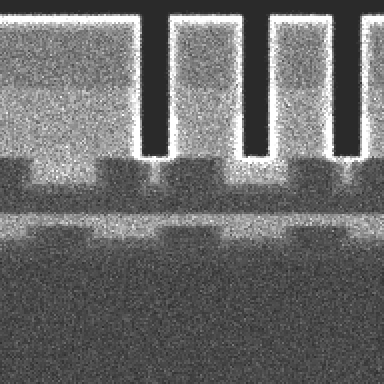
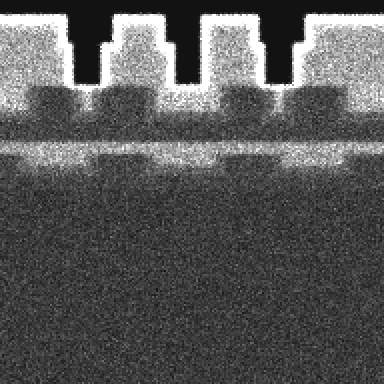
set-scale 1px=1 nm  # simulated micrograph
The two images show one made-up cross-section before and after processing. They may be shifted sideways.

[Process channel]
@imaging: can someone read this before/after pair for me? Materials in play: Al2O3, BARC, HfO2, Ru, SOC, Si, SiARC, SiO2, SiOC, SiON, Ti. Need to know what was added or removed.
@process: SOC removed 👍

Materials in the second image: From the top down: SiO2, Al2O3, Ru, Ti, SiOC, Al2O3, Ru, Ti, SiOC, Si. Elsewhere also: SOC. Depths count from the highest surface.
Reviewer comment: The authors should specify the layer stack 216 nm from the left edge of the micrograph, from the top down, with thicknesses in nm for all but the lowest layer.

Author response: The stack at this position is SiO2 54, Al2O3 16, Ru 26, Ti 10, SiOC 20, Al2O3 12, Ti 22, SiOC 14, Si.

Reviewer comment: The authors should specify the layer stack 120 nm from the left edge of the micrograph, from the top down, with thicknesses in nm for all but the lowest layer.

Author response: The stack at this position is SiO2 54, Al2O3 16, SiOC 56, Al2O3 12, SiOC 36, Si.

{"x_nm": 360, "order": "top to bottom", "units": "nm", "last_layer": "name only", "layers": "SiO2 54, Al2O3 16, Ru 26, Ti 10, SiOC 20, Al2O3 12, SiOC 36, Si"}